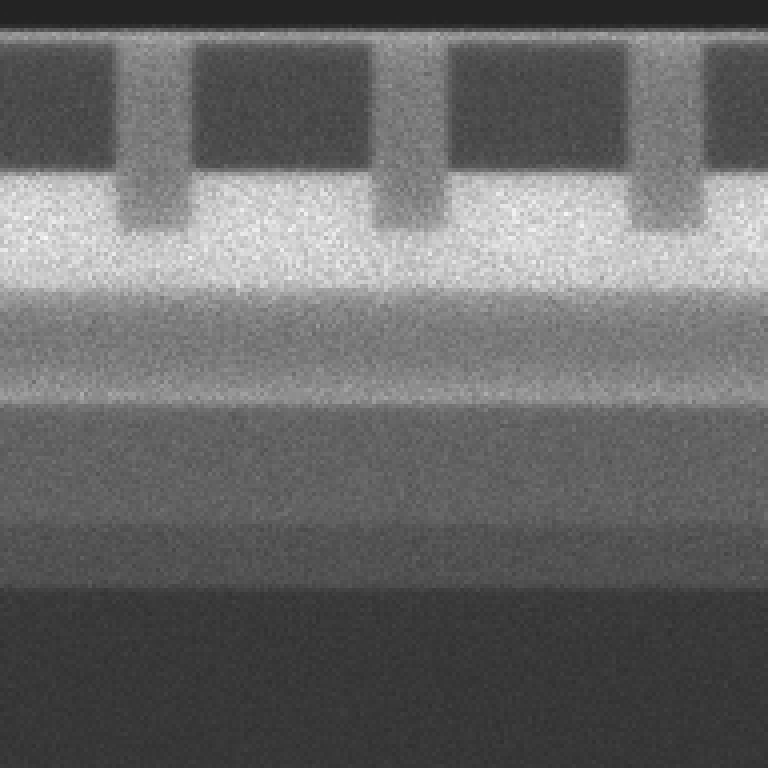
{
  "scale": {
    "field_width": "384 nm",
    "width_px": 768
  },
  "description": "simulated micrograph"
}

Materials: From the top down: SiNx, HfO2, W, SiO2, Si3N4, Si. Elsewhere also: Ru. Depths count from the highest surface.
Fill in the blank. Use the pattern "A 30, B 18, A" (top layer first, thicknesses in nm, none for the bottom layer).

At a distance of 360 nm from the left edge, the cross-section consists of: SiNx 70, HfO2 58, W 58, SiO2 60, Si3N4 32, Si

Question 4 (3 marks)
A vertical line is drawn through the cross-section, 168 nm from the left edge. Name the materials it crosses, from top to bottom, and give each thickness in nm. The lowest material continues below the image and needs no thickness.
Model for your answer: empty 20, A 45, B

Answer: SiNx 70, HfO2 58, W 58, SiO2 60, Si3N4 32, Si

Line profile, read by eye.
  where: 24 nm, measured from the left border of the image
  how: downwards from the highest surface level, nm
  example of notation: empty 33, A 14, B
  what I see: SiNx 70, HfO2 58, W 58, SiO2 60, Si3N4 32, Si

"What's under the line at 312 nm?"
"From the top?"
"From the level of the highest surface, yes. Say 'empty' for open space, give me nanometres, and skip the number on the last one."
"SiNx 70, HfO2 58, W 58, SiO2 60, Si3N4 32, Si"